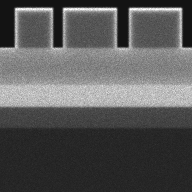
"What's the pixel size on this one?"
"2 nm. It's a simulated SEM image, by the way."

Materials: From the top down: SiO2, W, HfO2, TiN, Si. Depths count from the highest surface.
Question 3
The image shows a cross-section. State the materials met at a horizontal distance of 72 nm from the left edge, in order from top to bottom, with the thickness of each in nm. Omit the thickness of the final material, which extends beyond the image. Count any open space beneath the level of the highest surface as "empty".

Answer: SiO2 80, W 74, HfO2 44, TiN 42, Si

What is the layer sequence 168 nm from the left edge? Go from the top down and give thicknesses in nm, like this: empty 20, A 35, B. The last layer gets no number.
SiO2 80, W 74, HfO2 44, TiN 42, Si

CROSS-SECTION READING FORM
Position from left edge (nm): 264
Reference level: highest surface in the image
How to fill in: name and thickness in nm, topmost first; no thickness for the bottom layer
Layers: SiO2 80, W 74, HfO2 44, TiN 42, Si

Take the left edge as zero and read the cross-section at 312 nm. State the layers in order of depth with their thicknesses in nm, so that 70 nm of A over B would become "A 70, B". SiO2 80, W 74, HfO2 44, TiN 42, Si